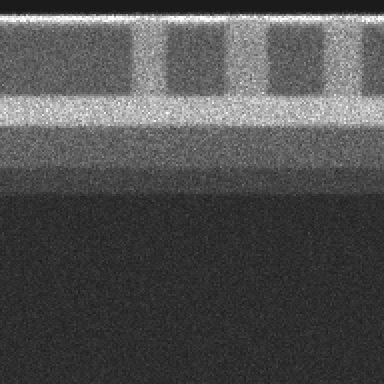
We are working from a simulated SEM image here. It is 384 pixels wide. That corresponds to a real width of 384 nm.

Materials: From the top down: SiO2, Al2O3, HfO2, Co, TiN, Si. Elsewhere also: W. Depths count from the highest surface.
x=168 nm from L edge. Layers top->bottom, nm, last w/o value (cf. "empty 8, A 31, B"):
SiO2 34, Al2O3 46, HfO2 30, Co 42, TiN 26, Si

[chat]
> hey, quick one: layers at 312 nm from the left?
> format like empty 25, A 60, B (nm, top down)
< SiO2 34, Al2O3 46, HfO2 30, Co 42, TiN 26, Si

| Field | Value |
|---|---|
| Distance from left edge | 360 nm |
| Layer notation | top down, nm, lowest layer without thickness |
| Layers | W 80, HfO2 30, Co 42, TiN 26, Si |